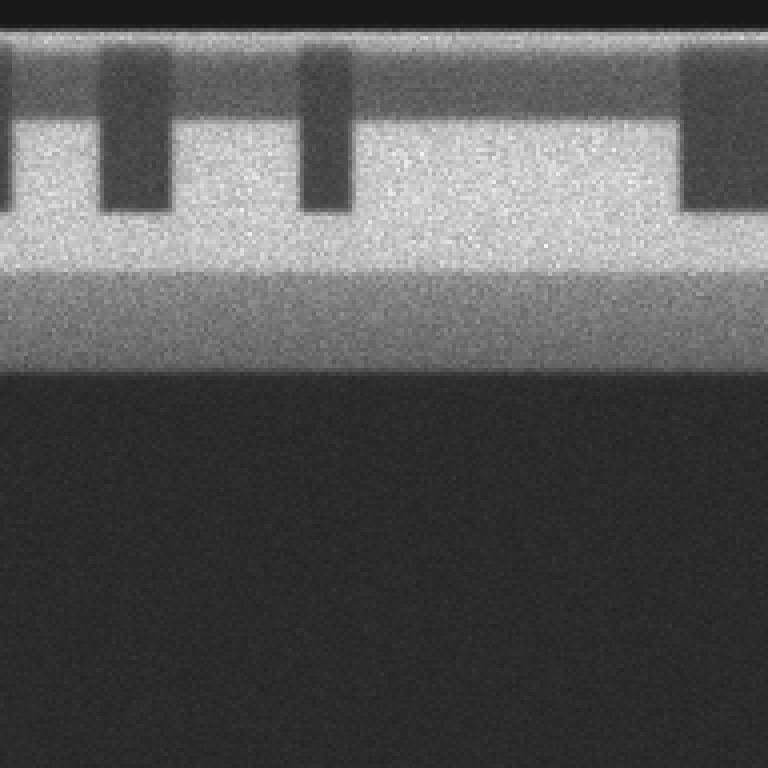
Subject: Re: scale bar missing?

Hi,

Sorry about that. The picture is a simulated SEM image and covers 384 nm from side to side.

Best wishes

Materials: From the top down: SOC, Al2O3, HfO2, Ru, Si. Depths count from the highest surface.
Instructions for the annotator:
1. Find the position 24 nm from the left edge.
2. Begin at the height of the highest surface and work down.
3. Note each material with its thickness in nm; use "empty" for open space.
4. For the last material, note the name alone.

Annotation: SOC 6, Al2O3 38, HfO2 76, Ru 50, Si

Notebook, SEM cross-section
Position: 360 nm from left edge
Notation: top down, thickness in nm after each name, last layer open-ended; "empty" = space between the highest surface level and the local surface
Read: SOC 90, HfO2 30, Ru 50, Si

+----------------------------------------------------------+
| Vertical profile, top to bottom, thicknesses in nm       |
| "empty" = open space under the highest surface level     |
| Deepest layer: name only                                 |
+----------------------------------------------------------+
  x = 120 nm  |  SOC 6, Al2O3 38, HfO2 76, Ru 50, Si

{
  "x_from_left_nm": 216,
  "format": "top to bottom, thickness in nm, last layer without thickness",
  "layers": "SOC 6, Al2O3 38, HfO2 76, Ru 50, Si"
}